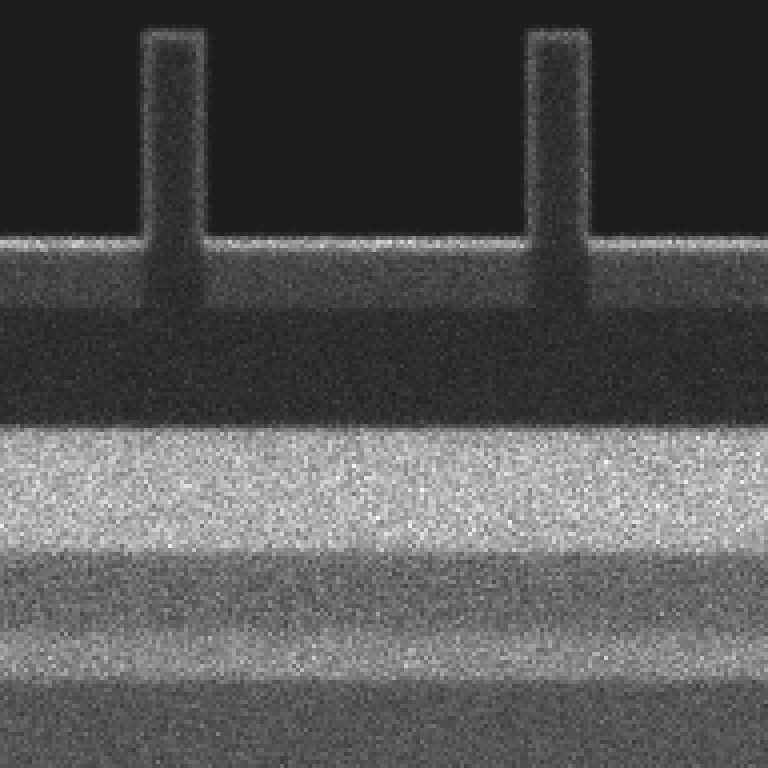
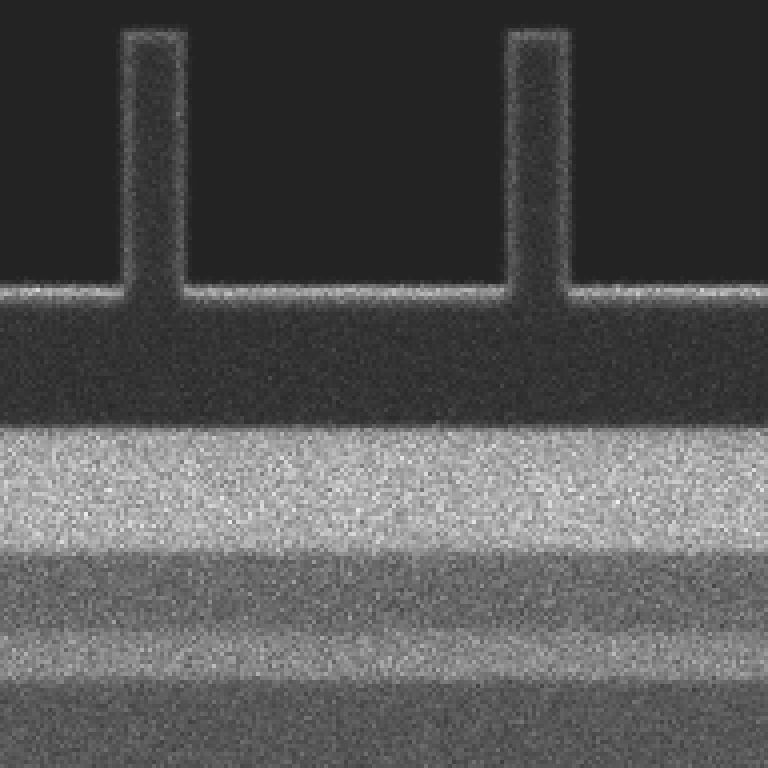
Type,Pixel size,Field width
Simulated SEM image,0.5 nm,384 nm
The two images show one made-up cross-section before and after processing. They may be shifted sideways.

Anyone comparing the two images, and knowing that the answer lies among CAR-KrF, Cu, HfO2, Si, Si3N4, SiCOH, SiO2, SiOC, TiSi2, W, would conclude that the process removed Si3N4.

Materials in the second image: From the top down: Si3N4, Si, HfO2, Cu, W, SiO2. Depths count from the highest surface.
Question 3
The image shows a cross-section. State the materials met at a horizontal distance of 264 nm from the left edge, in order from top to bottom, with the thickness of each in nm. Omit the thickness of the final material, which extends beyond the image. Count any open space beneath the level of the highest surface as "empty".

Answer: Si 198, HfO2 62, Cu 40, W 24, SiO2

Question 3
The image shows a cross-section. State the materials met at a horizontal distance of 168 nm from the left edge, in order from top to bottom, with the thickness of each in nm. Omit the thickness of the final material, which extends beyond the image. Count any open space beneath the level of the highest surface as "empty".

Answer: empty 128, Si3N4 10, Si 60, HfO2 62, Cu 40, W 24, SiO2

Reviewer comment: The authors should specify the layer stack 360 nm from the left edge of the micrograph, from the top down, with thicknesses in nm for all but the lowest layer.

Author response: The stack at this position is empty 128, Si3N4 10, Si 60, HfO2 62, Cu 40, W 24, SiO2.